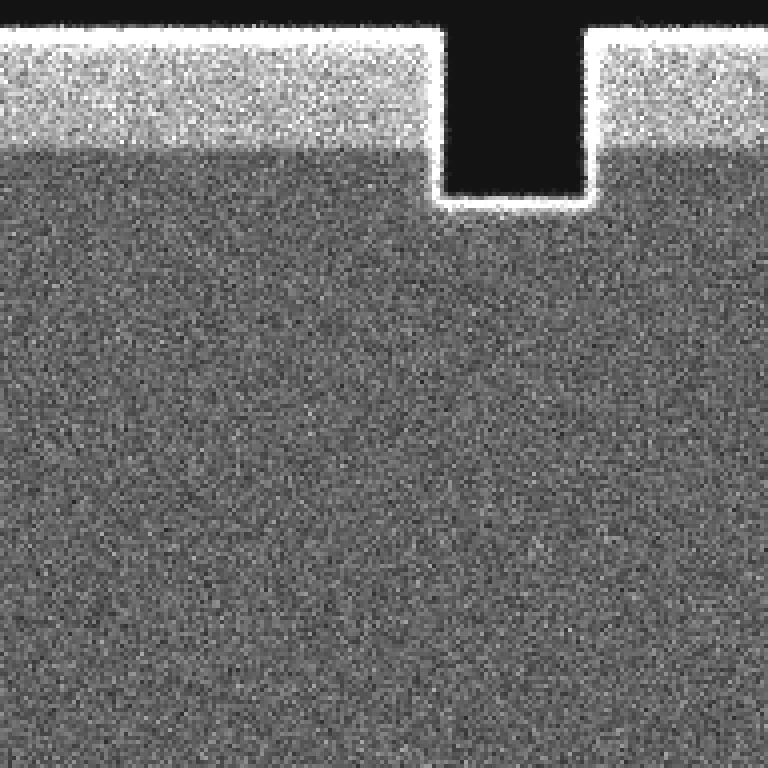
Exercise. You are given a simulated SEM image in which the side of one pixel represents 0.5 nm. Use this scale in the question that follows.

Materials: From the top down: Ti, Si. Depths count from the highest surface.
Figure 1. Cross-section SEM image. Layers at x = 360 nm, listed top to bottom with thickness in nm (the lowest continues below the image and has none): Ti 58, Si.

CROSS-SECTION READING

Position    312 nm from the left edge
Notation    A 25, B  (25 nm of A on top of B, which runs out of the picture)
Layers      Ti 58, Si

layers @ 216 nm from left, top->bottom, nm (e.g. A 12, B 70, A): Ti 58, Si